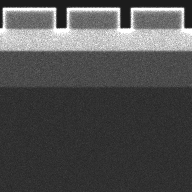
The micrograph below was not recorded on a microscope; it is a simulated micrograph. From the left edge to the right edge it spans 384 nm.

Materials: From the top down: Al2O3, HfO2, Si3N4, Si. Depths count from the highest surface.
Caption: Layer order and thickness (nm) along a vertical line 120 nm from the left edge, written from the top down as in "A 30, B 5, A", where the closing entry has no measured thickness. empty 42, HfO2 44, Si3N4 72, Si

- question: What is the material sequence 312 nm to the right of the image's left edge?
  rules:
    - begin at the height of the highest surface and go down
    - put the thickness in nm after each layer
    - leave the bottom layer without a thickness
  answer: Al2O3 42, HfO2 44, Si3N4 72, Si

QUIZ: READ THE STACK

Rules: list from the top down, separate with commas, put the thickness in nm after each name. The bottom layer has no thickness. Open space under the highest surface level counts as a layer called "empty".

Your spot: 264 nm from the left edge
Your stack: Al2O3 42, HfO2 44, Si3N4 72, Si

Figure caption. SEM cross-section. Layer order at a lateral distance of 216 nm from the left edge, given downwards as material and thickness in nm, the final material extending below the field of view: Al2O3 42, HfO2 44, Si3N4 72, Si